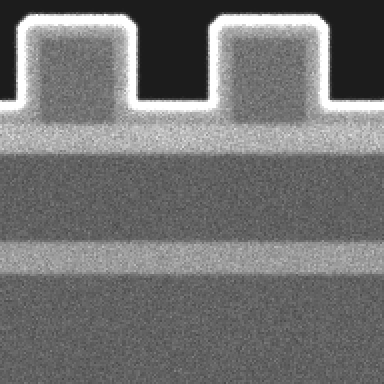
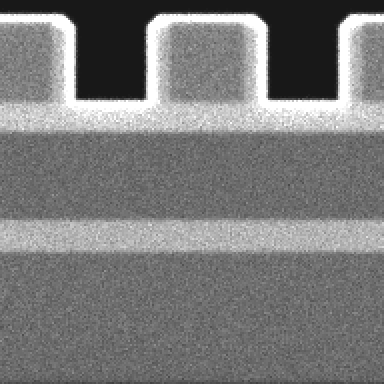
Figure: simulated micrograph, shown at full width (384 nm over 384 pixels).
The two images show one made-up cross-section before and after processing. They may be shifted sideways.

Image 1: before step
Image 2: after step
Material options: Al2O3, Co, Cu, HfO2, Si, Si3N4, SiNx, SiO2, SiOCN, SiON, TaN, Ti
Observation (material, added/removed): SiO2, removed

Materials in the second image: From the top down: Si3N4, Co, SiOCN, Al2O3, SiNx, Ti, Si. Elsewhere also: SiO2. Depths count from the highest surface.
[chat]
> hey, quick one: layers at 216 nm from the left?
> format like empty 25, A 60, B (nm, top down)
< Si3N4 86, Co 30, SiOCN 88, Al2O3 32, SiNx 56, Ti 74, Si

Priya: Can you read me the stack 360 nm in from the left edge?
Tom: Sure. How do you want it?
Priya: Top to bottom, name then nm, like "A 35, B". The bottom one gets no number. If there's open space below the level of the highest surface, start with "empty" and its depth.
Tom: SiO2 86, Co 30, SiOCN 88, Al2O3 32, SiNx 56, Ti 74, Si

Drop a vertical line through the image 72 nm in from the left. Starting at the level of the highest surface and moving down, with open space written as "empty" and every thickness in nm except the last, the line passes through empty 10, SiO2 76, Co 30, SiOCN 88, Al2O3 32, SiNx 56, Ti 74, Si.